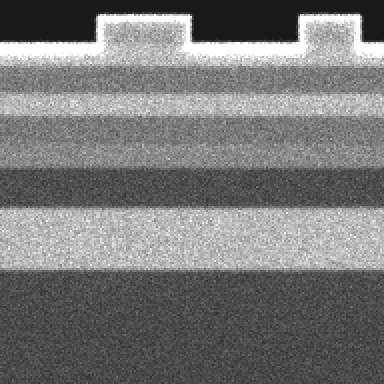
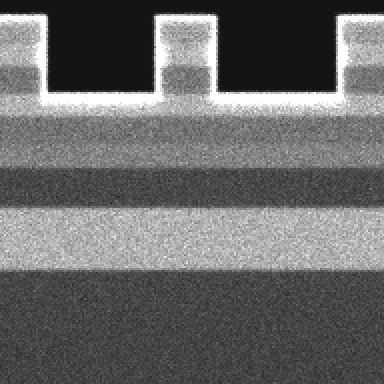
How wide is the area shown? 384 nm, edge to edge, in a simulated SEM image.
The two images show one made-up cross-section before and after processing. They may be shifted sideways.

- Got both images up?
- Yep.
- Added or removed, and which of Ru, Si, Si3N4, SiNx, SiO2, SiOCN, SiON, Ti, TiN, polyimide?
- removed, SiNx and SiO2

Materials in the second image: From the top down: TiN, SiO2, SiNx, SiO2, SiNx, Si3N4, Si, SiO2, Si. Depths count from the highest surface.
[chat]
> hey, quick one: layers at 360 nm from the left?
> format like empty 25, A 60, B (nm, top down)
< TiN 28, SiO2 22, SiNx 28, SiO2 22, SiNx 28, Si3N4 24, Si 40, SiO2 62, Si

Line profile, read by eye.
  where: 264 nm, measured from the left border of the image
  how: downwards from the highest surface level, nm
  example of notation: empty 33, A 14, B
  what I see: empty 78, SiO2 22, SiNx 28, Si3N4 24, Si 40, SiO2 62, Si